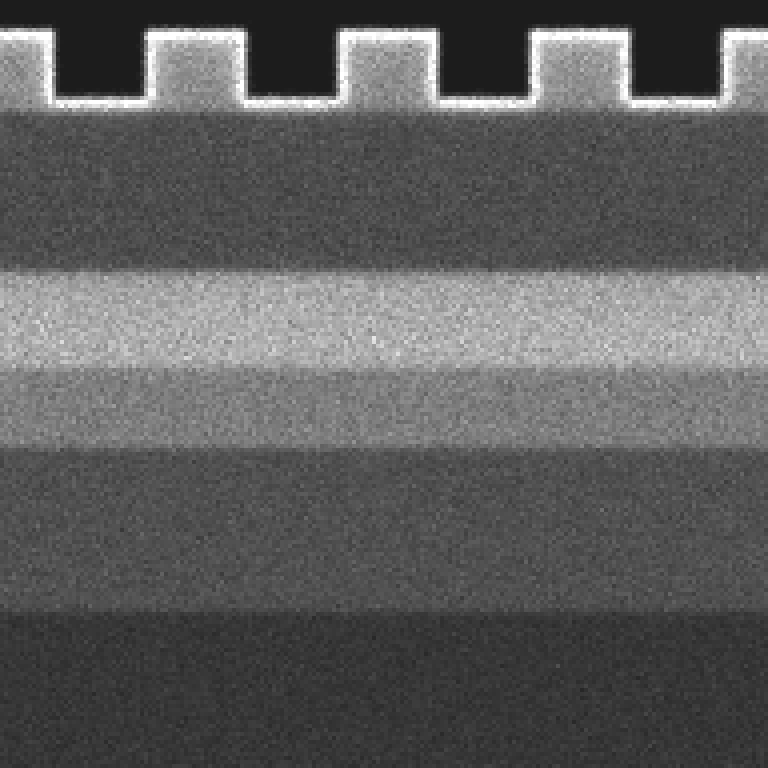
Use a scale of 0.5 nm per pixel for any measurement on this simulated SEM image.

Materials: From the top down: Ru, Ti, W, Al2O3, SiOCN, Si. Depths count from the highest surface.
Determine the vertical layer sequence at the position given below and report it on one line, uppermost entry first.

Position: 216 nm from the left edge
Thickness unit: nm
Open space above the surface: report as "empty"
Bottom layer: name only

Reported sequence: Ru 40, Ti 80, W 48, Al2O3 40, SiOCN 82, Si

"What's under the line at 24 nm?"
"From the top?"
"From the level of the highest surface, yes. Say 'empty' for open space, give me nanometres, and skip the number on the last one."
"Ru 40, Ti 80, W 48, Al2O3 40, SiOCN 82, Si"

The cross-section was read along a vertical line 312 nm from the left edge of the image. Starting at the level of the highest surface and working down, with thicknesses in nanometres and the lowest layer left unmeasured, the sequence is Ru 40, Ti 80, W 48, Al2O3 40, SiOCN 82, Si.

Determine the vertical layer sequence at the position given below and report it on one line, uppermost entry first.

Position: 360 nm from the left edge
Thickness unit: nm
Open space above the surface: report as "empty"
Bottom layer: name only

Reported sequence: empty 34, Ru 6, Ti 80, W 48, Al2O3 40, SiOCN 82, Si